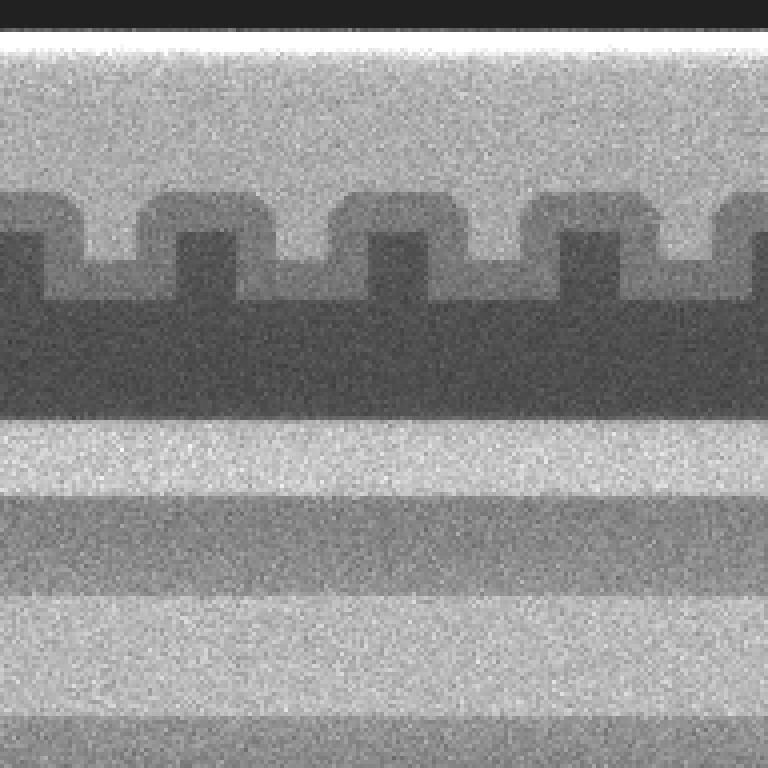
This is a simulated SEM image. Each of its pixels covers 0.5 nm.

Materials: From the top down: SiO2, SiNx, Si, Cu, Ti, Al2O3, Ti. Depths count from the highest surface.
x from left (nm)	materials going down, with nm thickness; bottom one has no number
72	SiO2 86, SiNx 48, Si 60, Cu 38, Ti 50, Al2O3 60, Ti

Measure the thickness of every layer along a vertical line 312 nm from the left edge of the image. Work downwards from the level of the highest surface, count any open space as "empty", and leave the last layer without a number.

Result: SiO2 80, SiNx 54, Si 60, Cu 38, Ti 50, Al2O3 60, Ti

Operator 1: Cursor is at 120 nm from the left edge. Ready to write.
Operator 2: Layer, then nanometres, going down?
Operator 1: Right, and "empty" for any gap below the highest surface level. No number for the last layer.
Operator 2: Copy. SiO2 80, SiNx 54, Si 60, Cu 38, Ti 50, Al2O3 60, Ti